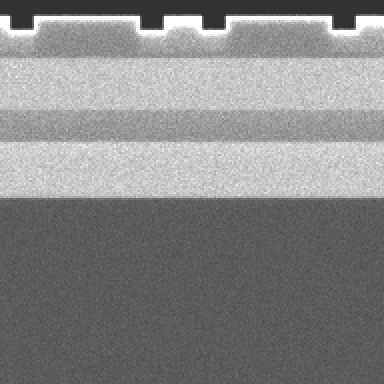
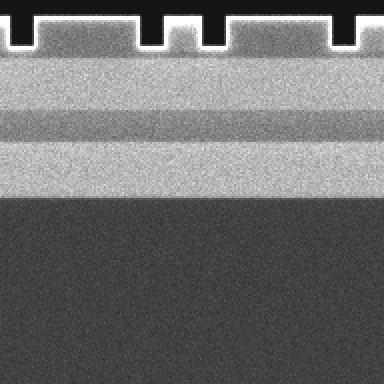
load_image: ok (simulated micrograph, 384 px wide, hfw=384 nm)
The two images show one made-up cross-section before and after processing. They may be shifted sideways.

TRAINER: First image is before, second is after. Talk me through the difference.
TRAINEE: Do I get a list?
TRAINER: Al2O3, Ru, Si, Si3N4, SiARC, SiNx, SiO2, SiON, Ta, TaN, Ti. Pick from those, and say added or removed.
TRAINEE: removed: Si3N4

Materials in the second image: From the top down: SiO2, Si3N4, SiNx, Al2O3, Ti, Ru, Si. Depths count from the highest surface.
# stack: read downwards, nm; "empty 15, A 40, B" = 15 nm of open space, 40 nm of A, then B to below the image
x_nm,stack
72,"SiNx 42, Al2O3 52, Ti 32, Ru 56, Si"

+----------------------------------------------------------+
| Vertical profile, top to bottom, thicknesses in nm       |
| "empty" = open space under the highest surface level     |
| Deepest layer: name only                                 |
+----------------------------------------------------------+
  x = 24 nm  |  empty 30, Si3N4 6, SiNx 6, Al2O3 52, Ti 32, Ru 56, Si